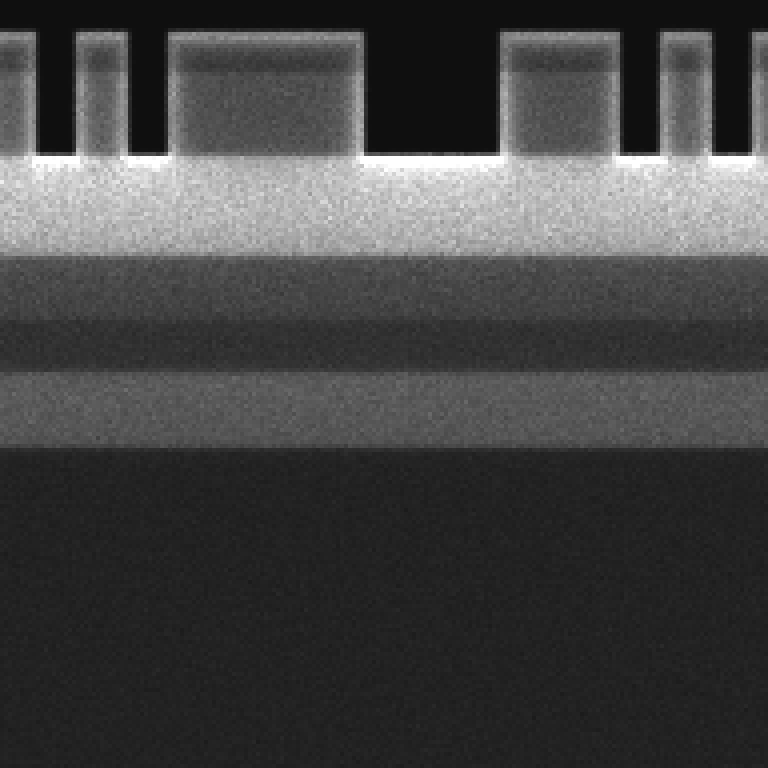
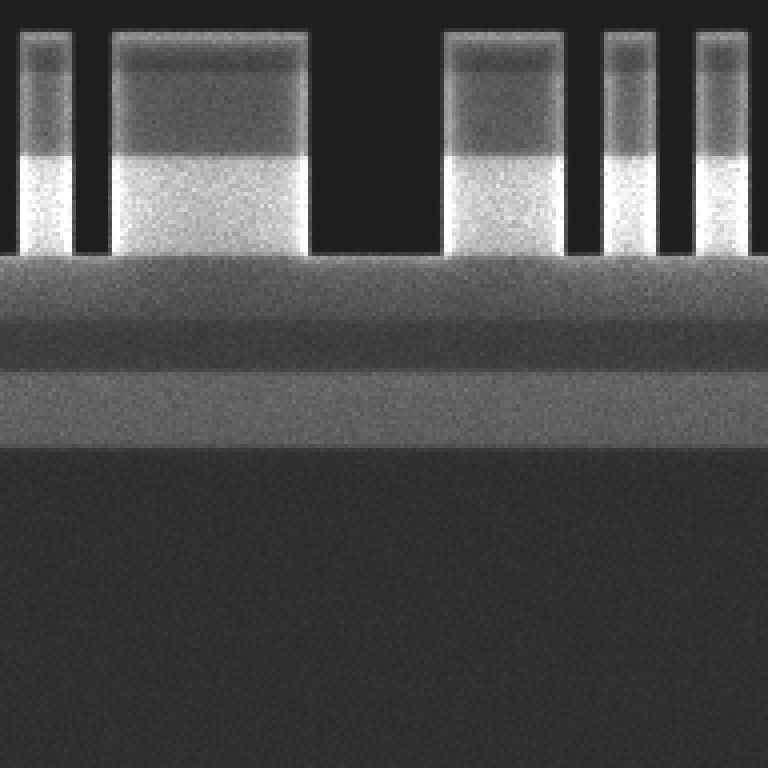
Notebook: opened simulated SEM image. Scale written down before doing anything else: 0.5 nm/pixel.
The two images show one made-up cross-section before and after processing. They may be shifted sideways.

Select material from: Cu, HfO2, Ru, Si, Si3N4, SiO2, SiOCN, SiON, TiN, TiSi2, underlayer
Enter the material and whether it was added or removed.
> HfO2 / removed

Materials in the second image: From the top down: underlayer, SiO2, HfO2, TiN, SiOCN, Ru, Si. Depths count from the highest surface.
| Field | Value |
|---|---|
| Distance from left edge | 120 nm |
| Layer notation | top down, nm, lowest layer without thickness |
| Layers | underlayer 20, SiO2 42, HfO2 50, TiN 32, SiOCN 26, Ru 38, Si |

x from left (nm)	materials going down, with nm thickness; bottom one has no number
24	underlayer 20, SiO2 42, HfO2 50, TiN 32, SiOCN 26, Ru 38, Si